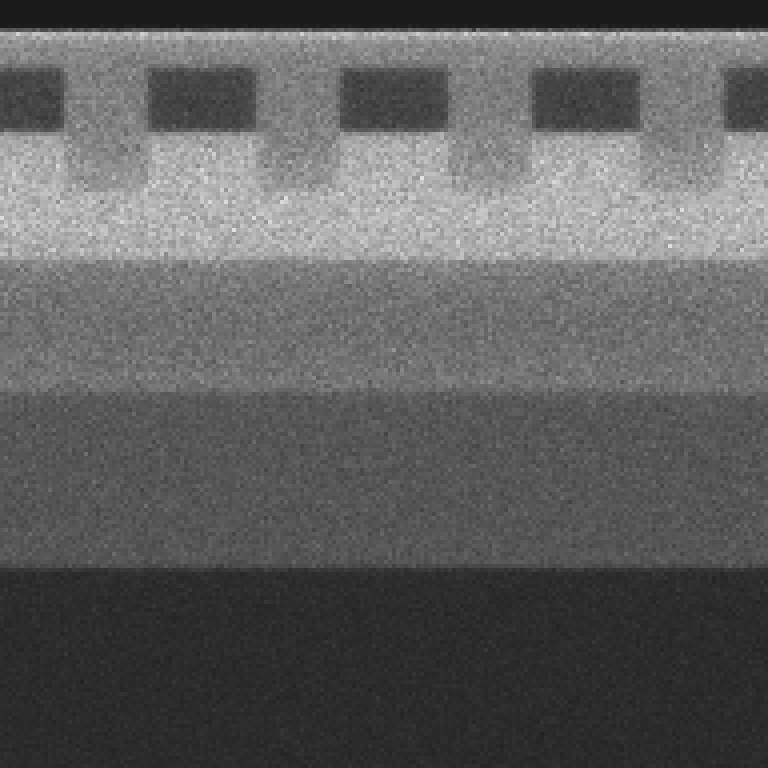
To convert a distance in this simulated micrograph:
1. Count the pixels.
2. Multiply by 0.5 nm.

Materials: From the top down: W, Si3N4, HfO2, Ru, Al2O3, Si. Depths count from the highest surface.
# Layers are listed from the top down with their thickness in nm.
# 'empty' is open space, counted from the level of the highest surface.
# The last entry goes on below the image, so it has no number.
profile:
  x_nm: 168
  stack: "W 80, HfO2 34, Ru 66, Al2O3 88, Si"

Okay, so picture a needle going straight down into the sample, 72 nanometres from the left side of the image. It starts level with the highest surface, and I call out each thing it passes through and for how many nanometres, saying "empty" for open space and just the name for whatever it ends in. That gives W 80, HfO2 34, Ru 66, Al2O3 88, Si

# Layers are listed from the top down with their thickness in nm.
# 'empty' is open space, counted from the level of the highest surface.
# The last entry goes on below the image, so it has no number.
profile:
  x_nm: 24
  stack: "W 18, Si3N4 32, HfO2 64, Ru 66, Al2O3 88, Si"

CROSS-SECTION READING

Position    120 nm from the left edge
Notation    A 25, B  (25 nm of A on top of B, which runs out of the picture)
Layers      W 18, Si3N4 32, HfO2 64, Ru 66, Al2O3 88, Si